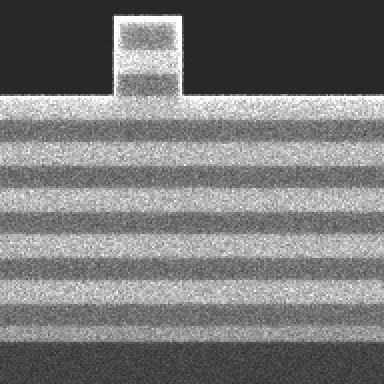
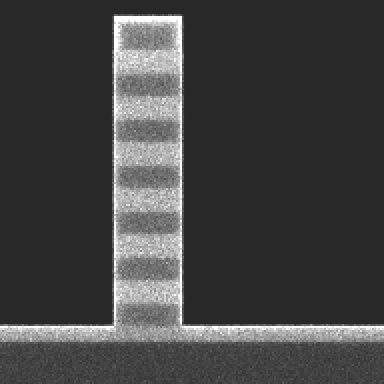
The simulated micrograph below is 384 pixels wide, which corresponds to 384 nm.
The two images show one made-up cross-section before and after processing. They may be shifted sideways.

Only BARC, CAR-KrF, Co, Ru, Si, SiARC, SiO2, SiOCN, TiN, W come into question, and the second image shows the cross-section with TiN and W removed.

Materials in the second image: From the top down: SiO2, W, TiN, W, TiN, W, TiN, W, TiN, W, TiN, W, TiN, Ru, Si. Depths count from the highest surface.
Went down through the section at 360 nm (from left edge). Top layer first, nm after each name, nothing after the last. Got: empty 310, Ru 16, Si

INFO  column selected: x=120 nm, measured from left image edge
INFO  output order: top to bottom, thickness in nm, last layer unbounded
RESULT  SiO2 34, W 24, TiN 22, W 24, TiN 22, W 24, TiN 22, W 24, TiN 22, W 24, TiN 22, W 24, TiN 22, Ru 16, Si